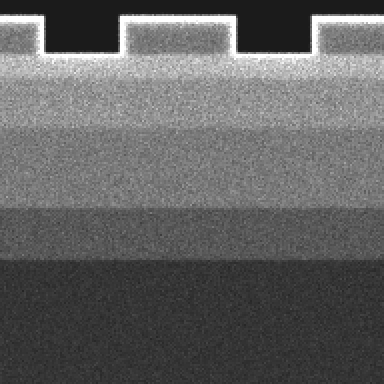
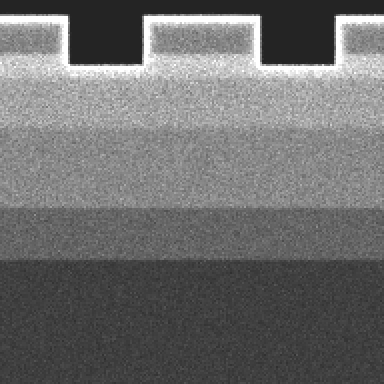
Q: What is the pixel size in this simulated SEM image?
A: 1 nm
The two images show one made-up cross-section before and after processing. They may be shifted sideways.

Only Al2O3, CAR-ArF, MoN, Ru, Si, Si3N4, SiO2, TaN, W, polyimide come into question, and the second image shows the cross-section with W removed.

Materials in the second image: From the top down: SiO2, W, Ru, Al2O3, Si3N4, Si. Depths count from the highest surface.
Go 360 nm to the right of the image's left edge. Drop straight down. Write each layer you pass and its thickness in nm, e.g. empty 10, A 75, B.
SiO2 38, W 24, Ru 50, Al2O3 80, Si3N4 52, Si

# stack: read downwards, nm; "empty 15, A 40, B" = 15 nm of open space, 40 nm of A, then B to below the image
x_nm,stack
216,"SiO2 38, W 24, Ru 50, Al2O3 80, Si3N4 52, Si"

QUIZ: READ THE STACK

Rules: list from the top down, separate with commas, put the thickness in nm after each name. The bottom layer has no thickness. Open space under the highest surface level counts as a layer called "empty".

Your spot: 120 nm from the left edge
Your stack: empty 50, W 12, Ru 50, Al2O3 80, Si3N4 52, Si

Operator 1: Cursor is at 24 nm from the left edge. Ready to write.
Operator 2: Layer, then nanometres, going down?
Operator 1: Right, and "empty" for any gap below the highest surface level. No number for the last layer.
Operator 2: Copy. SiO2 38, W 24, Ru 50, Al2O3 80, Si3N4 52, Si